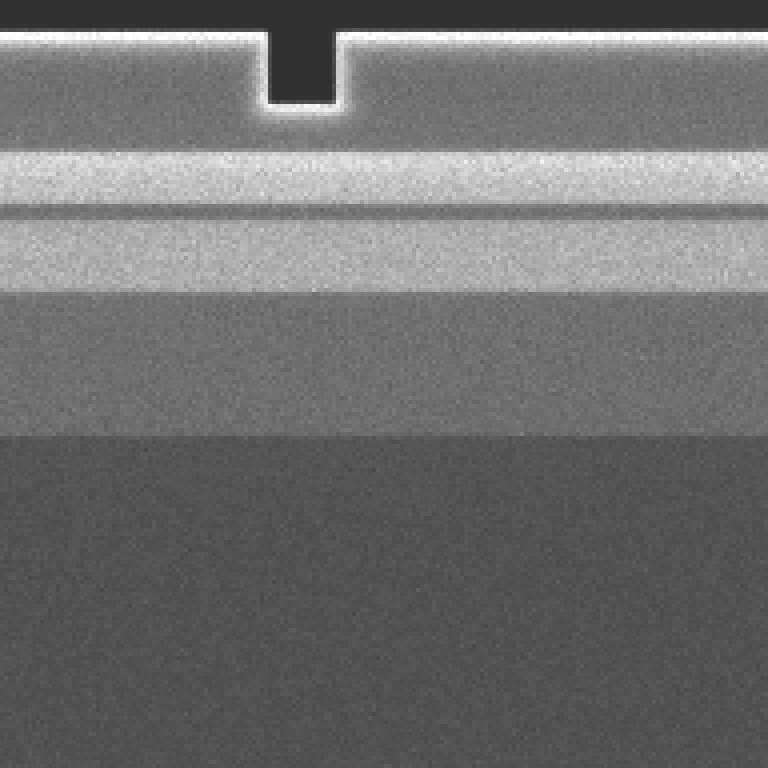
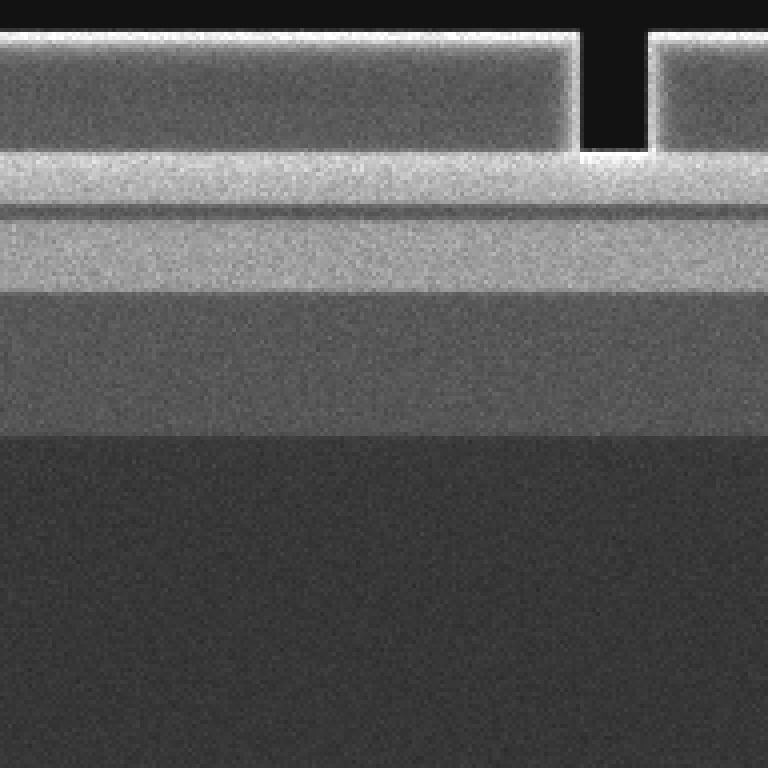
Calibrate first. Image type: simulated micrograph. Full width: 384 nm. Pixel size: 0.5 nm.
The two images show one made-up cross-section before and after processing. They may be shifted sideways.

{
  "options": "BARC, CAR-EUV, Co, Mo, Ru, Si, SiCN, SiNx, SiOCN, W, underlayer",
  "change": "removed",
  "material": "underlayer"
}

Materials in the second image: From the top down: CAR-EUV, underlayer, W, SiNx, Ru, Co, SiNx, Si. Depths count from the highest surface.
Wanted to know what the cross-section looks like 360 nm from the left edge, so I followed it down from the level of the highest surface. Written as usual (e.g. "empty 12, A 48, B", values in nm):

CAR-EUV 36, underlayer 24, W 26, SiNx 8, Ru 18, Co 18, SiNx 72, Si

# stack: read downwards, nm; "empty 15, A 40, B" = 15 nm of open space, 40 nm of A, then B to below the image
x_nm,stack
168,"CAR-EUV 36, underlayer 24, W 26, SiNx 8, Ru 18, Co 18, SiNx 72, Si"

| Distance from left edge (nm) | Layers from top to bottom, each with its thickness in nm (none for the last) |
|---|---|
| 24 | CAR-EUV 36, underlayer 24, W 26, SiNx 8, Ru 18, Co 18, SiNx 72, Si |